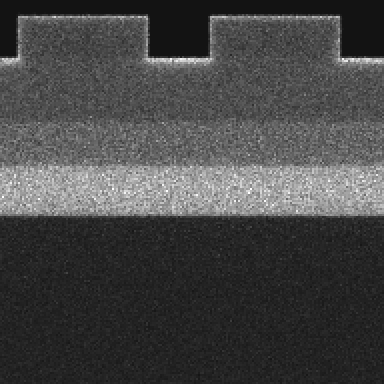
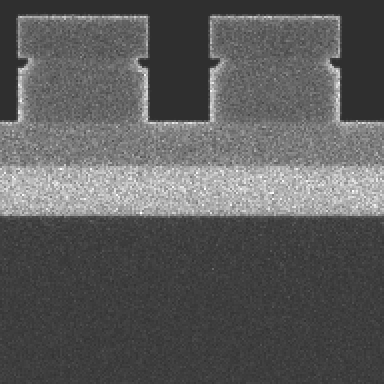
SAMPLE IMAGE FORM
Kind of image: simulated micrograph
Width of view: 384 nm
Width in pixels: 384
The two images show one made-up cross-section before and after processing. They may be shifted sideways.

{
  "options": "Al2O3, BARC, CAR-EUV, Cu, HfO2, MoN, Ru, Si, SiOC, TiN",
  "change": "removed",
  "material": "Al2O3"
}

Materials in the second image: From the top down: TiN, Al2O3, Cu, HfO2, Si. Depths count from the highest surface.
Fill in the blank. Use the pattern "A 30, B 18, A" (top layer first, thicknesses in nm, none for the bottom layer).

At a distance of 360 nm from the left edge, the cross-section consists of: empty 106, Cu 44, HfO2 50, Si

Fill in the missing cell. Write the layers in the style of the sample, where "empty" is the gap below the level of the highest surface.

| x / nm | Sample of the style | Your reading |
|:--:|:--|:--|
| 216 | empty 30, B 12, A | TiN 42, empty 8, Al2O3 56, Cu 44, HfO2 50, Si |